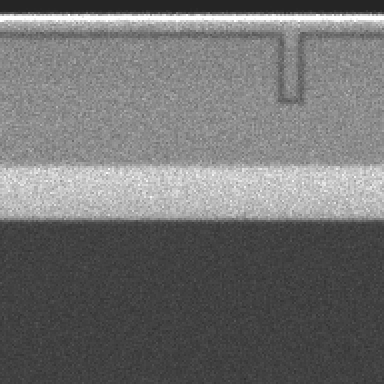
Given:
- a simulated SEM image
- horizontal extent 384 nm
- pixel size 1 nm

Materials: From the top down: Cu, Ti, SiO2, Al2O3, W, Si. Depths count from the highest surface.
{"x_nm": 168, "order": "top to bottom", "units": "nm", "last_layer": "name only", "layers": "Cu 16, Ti 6, SiO2 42, Al2O3 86, W 54, Si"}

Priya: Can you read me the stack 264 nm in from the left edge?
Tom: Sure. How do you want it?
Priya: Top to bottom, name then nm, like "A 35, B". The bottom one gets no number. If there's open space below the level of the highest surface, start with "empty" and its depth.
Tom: Cu 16, Ti 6, SiO2 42, Al2O3 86, W 54, Si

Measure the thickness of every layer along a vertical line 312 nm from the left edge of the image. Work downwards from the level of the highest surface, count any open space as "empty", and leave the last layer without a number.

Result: Cu 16, Ti 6, SiO2 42, Al2O3 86, W 54, Si